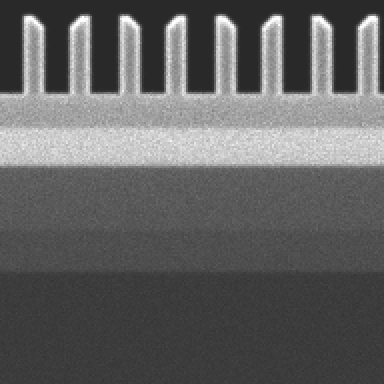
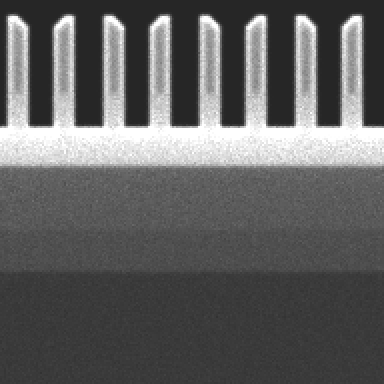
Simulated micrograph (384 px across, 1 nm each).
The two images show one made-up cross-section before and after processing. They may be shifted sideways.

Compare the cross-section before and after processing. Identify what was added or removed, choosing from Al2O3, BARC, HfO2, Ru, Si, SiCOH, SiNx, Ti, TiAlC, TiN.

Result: Ru removed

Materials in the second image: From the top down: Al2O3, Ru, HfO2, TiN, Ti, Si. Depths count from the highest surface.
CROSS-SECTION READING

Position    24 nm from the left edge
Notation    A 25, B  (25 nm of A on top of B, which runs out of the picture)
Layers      empty 8, Al2O3 70, Ru 34, HfO2 38, TiN 64, Ti 42, Si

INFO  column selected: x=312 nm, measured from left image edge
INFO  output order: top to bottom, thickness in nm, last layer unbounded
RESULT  empty 8, Al2O3 70, Ru 34, HfO2 38, TiN 64, Ti 42, Si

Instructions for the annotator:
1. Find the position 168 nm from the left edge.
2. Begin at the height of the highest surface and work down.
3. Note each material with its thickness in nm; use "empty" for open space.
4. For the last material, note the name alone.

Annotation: Al2O3 78, Ru 34, HfO2 38, TiN 64, Ti 42, Si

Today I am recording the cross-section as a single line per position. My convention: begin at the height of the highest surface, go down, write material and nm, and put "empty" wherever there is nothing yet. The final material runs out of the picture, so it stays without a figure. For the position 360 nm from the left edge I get Al2O3 78, Ru 34, HfO2 38, TiN 64, Ti 42, Si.